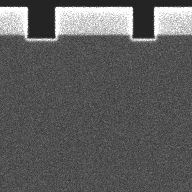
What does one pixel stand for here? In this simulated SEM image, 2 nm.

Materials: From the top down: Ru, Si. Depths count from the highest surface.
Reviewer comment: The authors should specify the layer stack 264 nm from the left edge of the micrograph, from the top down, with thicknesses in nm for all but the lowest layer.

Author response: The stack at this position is empty 62, Si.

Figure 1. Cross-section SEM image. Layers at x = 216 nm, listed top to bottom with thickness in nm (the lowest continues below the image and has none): Ru 54, Si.